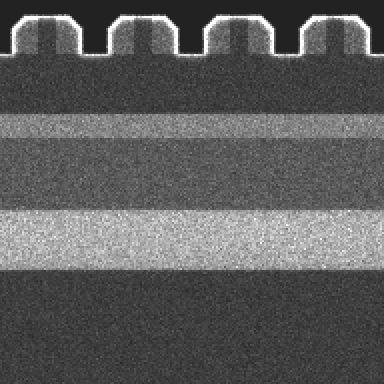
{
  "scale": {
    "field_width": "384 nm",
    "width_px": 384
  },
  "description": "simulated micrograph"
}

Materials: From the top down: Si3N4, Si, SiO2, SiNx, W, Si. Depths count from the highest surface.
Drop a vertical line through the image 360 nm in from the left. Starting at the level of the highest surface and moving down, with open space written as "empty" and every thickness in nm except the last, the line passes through empty 4, Si3N4 34, Si 60, SiO2 24, SiNx 72, W 60, Si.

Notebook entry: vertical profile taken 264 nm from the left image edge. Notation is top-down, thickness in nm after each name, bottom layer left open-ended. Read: empty 4, Si3N4 34, Si 60, SiO2 24, SiNx 72, W 60, Si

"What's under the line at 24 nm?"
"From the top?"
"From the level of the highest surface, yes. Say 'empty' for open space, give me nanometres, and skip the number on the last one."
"Si3N4 38, Si 60, SiO2 24, SiNx 72, W 60, Si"